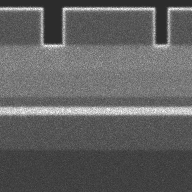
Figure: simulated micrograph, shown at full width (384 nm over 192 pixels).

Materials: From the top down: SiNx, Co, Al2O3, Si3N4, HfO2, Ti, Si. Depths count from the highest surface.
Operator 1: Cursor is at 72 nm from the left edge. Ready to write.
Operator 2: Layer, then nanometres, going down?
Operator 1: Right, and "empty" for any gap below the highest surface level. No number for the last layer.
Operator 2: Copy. SiNx 74, Co 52, Al2O3 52, Si3N4 20, HfO2 16, Ti 70, Si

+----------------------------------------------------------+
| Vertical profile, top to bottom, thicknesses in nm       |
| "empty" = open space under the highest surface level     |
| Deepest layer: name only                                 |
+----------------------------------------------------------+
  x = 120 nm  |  empty 74, Co 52, Al2O3 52, Si3N4 20, HfO2 16, Ti 70, Si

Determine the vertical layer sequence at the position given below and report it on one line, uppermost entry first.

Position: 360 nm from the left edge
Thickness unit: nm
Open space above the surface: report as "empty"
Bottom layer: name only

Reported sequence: SiNx 74, Co 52, Al2O3 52, Si3N4 20, HfO2 16, Ti 70, Si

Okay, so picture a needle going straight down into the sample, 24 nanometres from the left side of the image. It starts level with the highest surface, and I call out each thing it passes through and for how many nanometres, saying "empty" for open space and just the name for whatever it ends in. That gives SiNx 74, Co 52, Al2O3 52, Si3N4 20, HfO2 16, Ti 70, Si